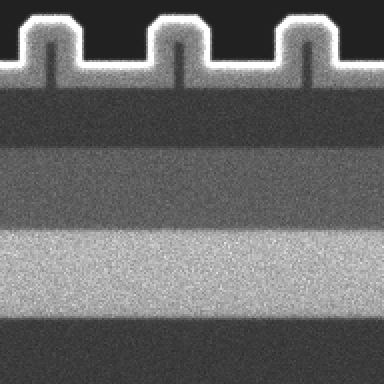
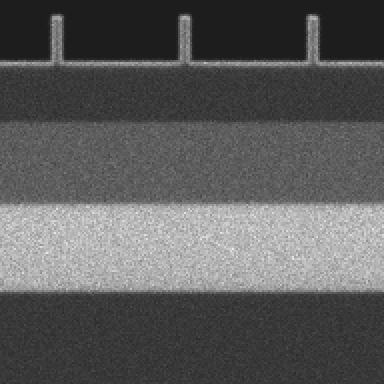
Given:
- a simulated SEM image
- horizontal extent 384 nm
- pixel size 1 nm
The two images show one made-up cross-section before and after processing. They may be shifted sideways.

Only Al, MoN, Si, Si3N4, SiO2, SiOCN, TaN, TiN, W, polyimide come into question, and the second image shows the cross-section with SiO2 removed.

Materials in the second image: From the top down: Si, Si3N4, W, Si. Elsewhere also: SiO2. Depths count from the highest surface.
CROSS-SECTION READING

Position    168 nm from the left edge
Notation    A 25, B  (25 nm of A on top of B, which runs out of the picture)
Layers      empty 46, Si 60, Si3N4 82, W 88, Si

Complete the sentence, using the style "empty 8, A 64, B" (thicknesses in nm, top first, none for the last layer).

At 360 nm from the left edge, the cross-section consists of empty 46, Si 60, Si3N4 82, W 88, Si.